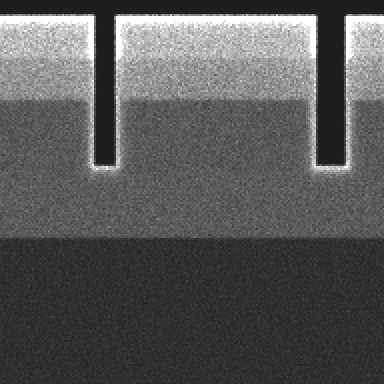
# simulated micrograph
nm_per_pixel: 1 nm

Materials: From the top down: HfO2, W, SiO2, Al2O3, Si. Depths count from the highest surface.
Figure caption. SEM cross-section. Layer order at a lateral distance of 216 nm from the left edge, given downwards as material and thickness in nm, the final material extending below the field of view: HfO2 42, W 42, SiO2 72, Al2O3 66, Si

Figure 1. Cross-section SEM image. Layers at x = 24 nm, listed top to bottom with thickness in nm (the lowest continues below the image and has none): HfO2 42, W 42, SiO2 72, Al2O3 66, Si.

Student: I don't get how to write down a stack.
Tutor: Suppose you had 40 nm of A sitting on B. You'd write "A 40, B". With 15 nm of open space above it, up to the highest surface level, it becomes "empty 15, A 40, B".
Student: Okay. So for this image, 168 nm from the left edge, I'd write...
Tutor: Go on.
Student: HfO2 42, W 42, SiO2 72, Al2O3 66, Si